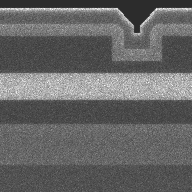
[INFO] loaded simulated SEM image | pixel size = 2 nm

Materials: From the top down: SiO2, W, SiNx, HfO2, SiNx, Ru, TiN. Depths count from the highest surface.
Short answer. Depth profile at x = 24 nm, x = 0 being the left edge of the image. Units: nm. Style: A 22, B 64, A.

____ SiO2 32, W 24, SiNx 74, HfO2 54, SiNx 48, Ru 82, TiN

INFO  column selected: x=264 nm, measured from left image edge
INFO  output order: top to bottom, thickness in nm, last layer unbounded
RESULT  empty 32, SiO2 50, W 24, SiNx 24, HfO2 54, SiNx 48, Ru 82, TiN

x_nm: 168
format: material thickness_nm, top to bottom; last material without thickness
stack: SiO2 32, W 24, SiNx 74, HfO2 54, SiNx 48, Ru 82, TiN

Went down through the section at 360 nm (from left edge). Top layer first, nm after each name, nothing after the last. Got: SiO2 32, W 24, SiNx 74, HfO2 54, SiNx 48, Ru 82, TiN